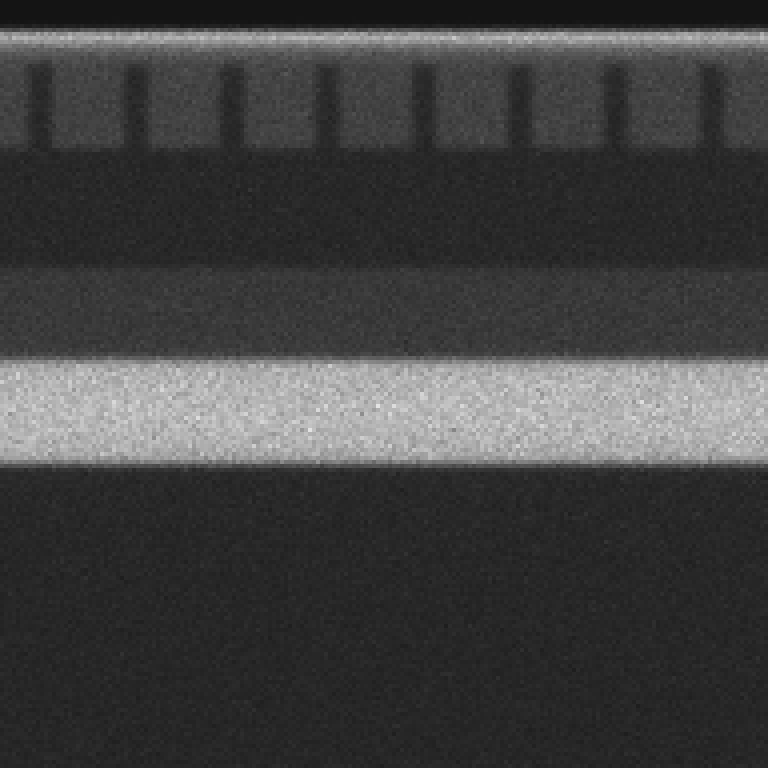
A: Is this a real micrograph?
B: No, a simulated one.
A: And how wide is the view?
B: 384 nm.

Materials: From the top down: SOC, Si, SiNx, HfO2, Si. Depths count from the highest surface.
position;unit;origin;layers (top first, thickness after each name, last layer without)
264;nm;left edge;SOC 16, Si 102, SiNx 46, HfO2 52, Si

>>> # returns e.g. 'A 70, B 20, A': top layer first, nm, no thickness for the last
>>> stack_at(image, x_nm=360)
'SOC 16, Si 102, SiNx 46, HfO2 52, Si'